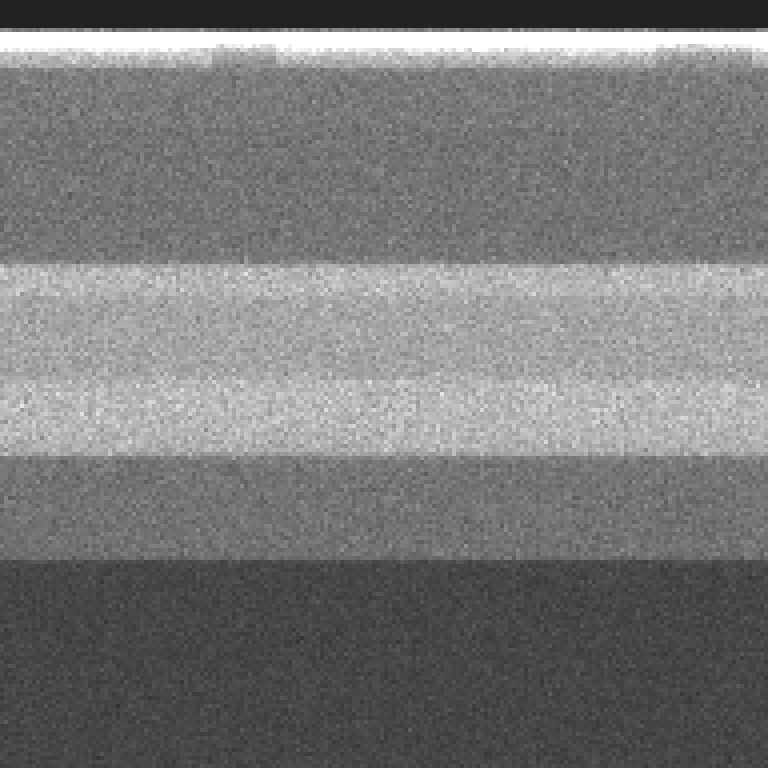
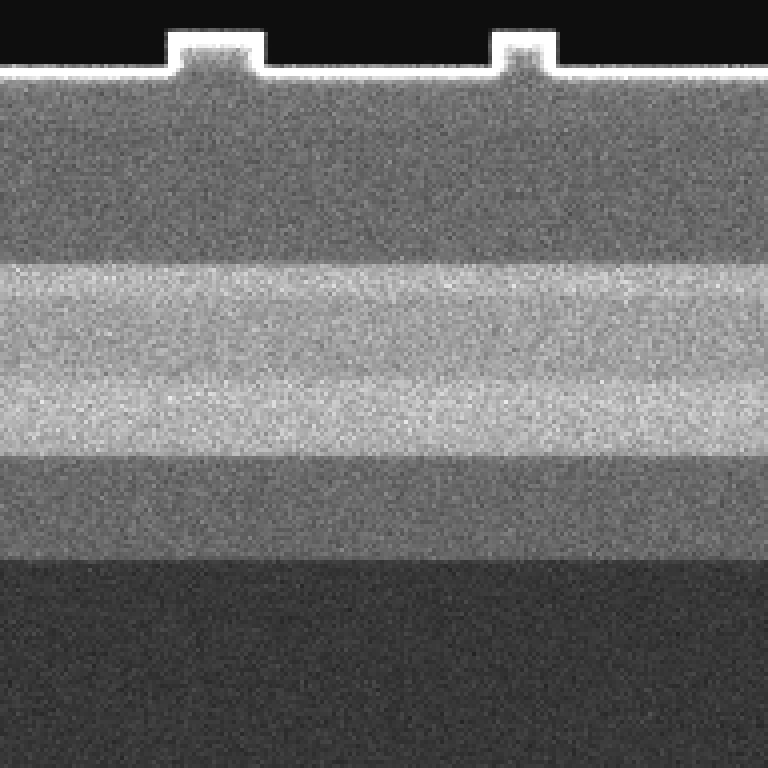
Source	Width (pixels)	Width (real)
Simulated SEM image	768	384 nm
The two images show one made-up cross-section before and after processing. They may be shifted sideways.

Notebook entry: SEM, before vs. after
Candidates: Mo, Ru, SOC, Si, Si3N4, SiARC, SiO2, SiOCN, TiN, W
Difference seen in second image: SiO2 removed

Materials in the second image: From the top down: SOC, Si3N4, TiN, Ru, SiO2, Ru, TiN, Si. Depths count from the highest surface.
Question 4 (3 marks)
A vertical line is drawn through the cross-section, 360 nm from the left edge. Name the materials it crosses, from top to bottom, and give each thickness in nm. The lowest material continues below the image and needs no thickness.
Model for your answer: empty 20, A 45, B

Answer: empty 18, Si3N4 30, TiN 68, Ru 16, SiO2 42, Ru 38, TiN 52, Si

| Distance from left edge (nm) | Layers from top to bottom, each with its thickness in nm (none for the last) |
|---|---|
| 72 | empty 18, Si3N4 30, TiN 68, Ru 16, SiO2 42, Ru 38, TiN 52, Si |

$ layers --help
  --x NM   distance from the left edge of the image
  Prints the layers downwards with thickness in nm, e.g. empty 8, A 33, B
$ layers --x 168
empty 18, Si3N4 30, TiN 68, Ru 16, SiO2 42, Ru 38, TiN 52, Si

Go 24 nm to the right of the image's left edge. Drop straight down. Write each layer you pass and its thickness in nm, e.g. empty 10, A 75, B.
empty 18, Si3N4 30, TiN 68, Ru 16, SiO2 42, Ru 38, TiN 52, Si